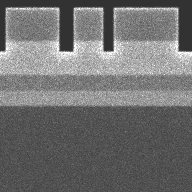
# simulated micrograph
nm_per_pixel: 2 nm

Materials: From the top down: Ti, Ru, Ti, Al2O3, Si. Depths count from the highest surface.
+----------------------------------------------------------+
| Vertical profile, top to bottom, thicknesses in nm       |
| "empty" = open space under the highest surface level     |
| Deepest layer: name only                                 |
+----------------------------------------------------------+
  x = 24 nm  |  Ti 66, Ru 68, Ti 32, Al2O3 30, Si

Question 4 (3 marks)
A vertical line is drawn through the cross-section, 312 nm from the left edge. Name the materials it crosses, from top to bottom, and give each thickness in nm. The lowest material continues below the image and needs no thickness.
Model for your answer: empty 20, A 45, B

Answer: Ti 66, Ru 68, Ti 32, Al2O3 30, Si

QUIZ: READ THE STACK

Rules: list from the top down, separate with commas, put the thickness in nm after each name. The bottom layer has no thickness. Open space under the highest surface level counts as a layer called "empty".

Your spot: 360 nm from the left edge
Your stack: empty 88, Ru 46, Ti 32, Al2O3 30, Si